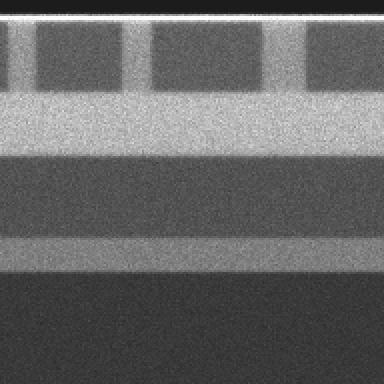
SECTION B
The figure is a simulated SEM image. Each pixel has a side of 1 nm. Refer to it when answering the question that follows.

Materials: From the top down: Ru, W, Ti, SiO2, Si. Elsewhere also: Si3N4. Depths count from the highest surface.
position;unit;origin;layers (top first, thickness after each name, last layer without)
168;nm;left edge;Si3N4 76, W 64, Ti 82, SiO2 34, Si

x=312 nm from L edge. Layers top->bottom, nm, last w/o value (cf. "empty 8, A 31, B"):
Si3N4 76, W 64, Ti 82, SiO2 34, Si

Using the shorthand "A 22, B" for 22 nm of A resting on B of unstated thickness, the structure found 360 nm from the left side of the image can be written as Si3N4 76, W 64, Ti 82, SiO2 34, Si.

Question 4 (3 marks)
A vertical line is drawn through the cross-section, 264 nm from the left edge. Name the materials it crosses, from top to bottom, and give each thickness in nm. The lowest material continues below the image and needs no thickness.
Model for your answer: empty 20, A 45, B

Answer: Ru 76, W 64, Ti 82, SiO2 34, Si